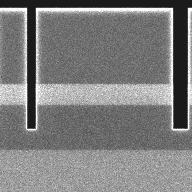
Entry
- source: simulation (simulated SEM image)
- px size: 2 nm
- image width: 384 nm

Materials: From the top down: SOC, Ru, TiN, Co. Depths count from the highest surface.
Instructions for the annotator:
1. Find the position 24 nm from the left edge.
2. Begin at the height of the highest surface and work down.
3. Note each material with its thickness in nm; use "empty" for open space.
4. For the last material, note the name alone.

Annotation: SOC 152, Ru 42, TiN 90, Co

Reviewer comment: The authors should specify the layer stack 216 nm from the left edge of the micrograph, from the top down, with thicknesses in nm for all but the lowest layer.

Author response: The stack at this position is SOC 152, Ru 42, TiN 90, Co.